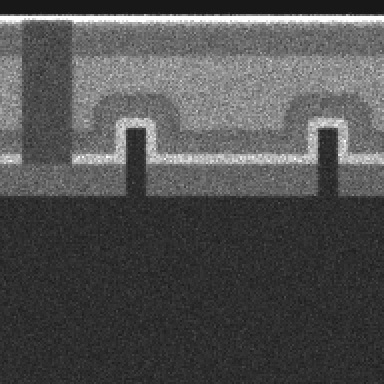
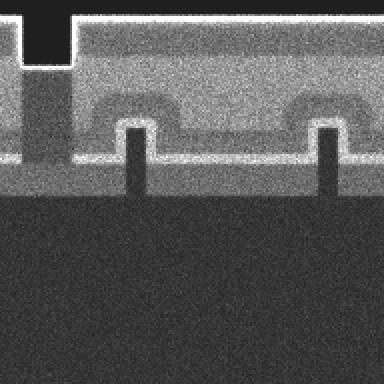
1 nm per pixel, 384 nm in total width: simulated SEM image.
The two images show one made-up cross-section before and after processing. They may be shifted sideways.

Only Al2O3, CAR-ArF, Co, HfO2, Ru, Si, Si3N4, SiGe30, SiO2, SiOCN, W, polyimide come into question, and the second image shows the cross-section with Si3N4 removed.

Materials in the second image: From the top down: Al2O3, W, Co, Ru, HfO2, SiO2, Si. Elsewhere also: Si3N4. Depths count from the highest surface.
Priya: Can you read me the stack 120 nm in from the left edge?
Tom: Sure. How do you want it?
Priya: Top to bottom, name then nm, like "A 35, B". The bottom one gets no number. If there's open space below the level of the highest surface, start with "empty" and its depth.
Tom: Al2O3 40, W 38, Co 10, Ru 14, HfO2 46, SiO2 32, Si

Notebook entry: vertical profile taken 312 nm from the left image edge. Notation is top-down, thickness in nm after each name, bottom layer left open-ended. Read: Al2O3 40, W 38, Co 10, Ru 14, HfO2 46, SiO2 32, Si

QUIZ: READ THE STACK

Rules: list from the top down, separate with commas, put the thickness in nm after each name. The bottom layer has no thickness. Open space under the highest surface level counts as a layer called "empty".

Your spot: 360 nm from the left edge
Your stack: Al2O3 40, W 42, Co 16, Ru 40, HfO2 10, SiO2 32, Si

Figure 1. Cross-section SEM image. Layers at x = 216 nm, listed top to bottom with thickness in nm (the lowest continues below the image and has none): Al2O3 40, W 74, Co 10, Ru 14, HfO2 10, SiO2 32, Si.